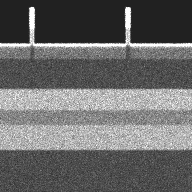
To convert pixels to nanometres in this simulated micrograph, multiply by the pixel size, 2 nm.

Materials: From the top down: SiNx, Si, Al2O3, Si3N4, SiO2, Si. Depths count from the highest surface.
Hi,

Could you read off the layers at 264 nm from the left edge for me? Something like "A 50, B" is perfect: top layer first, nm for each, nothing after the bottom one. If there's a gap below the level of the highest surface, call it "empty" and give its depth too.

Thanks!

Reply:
empty 72, SiNx 30, Si 60, Al2O3 42, Si3N4 30, SiO2 50, Si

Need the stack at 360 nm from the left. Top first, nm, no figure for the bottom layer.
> empty 72, SiNx 30, Si 60, Al2O3 42, Si3N4 30, SiO2 50, Si